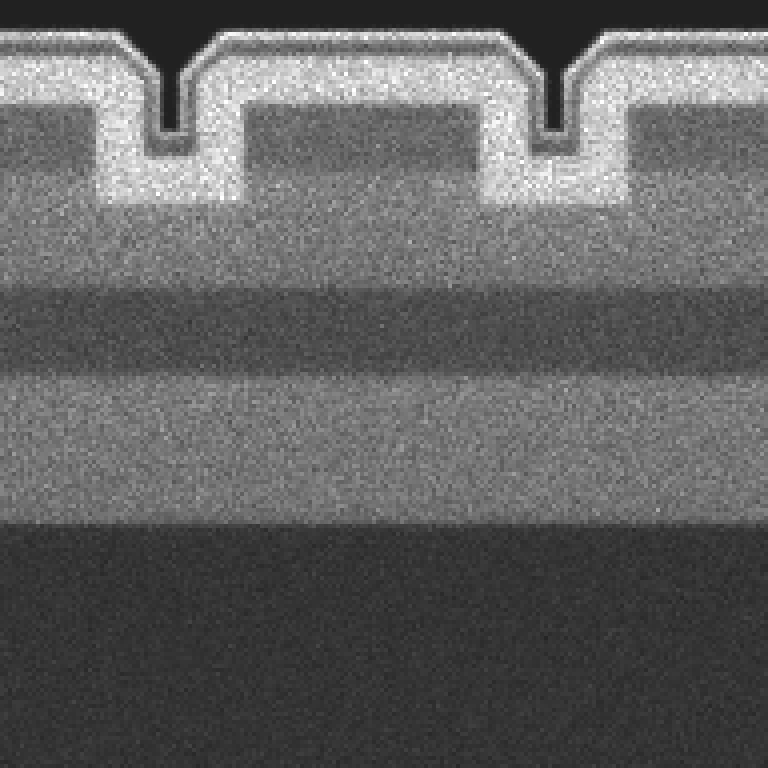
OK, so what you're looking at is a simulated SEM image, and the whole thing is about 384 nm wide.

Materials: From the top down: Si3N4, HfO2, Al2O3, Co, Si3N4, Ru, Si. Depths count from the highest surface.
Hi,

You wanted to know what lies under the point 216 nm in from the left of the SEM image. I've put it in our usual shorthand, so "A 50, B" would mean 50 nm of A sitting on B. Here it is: Si3N4 12, HfO2 24, Al2O3 34, Co 58, Si3N4 44, Ru 74, Si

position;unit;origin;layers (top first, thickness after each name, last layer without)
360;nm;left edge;Si3N4 12, HfO2 24, Al2O3 34, Co 58, Si3N4 44, Ru 74, Si